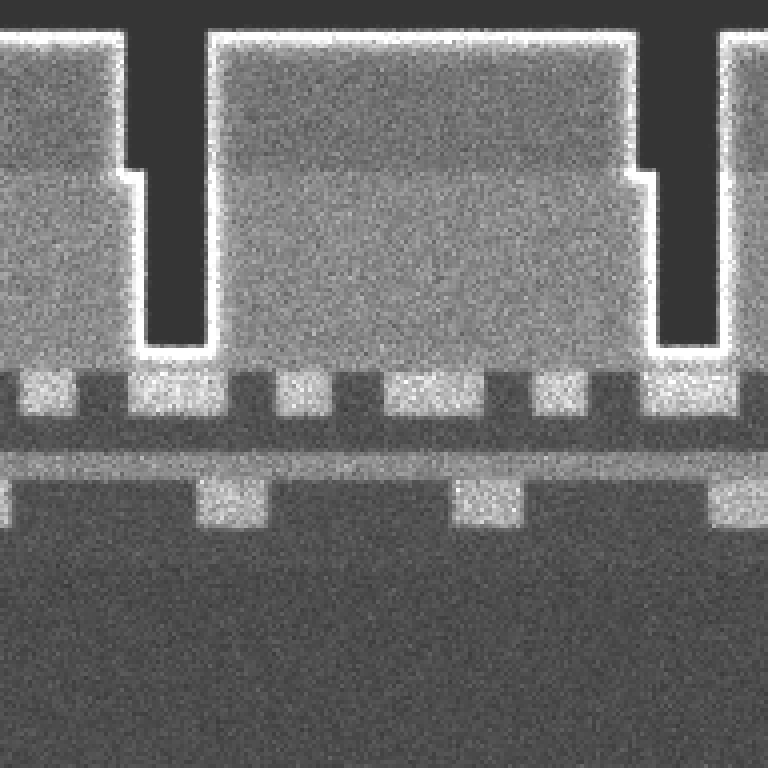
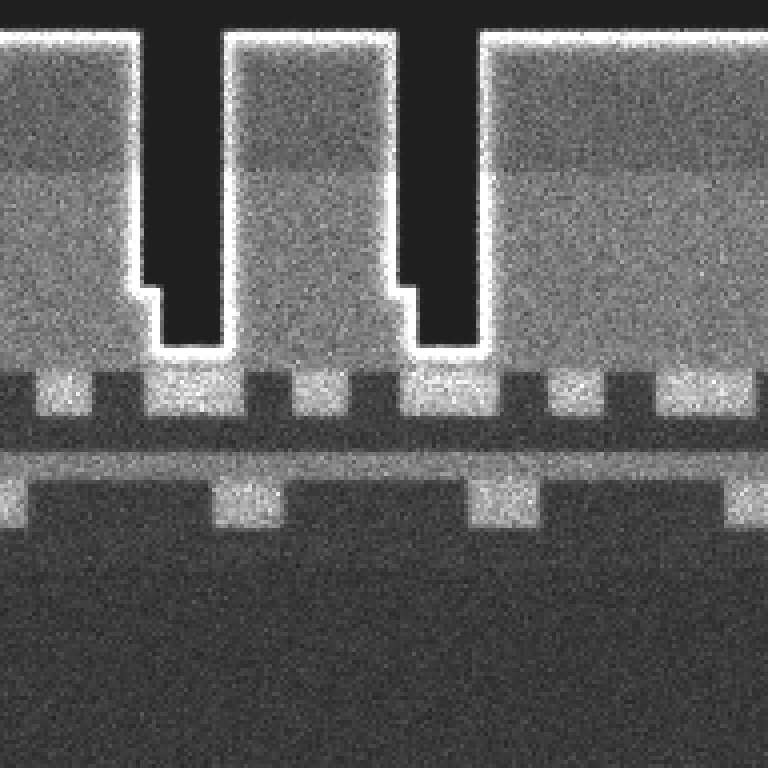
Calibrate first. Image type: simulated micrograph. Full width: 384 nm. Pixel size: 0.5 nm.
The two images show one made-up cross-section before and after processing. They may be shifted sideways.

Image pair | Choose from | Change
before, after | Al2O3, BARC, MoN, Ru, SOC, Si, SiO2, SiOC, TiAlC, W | SiO2 (removed)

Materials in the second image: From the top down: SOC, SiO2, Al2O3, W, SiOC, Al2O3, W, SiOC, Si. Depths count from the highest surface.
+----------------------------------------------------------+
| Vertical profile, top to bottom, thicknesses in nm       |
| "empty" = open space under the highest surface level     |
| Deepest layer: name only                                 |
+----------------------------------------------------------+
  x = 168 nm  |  SOC 70, SiO2 88, Al2O3 12, W 22, SiOC 18, Al2O3 14, SiOC 44, Si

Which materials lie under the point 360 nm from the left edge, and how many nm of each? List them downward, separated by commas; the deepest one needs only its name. SOC 70, SiO2 88, Al2O3 12, W 22, SiOC 18, Al2O3 14, SiOC 44, Si